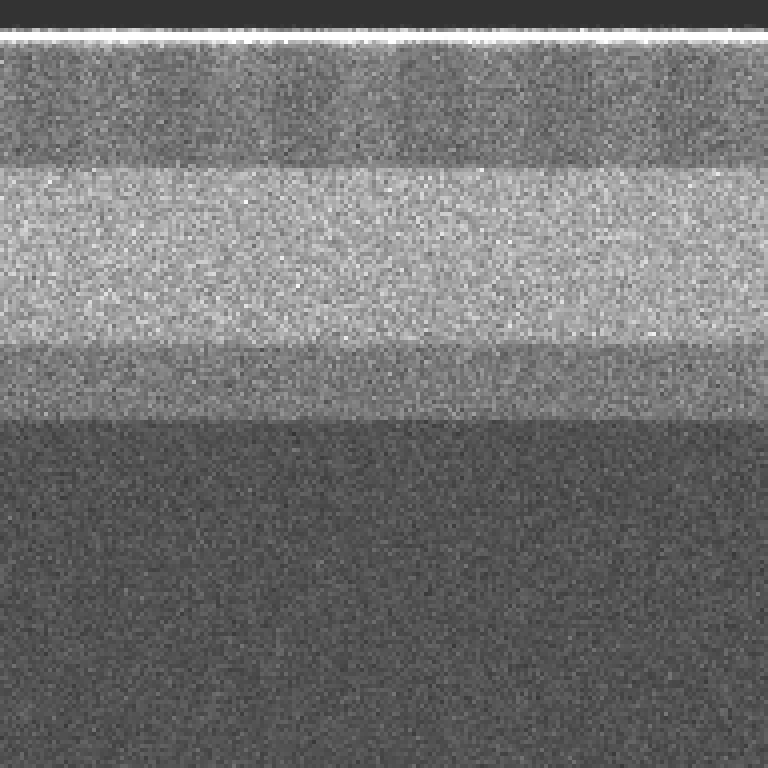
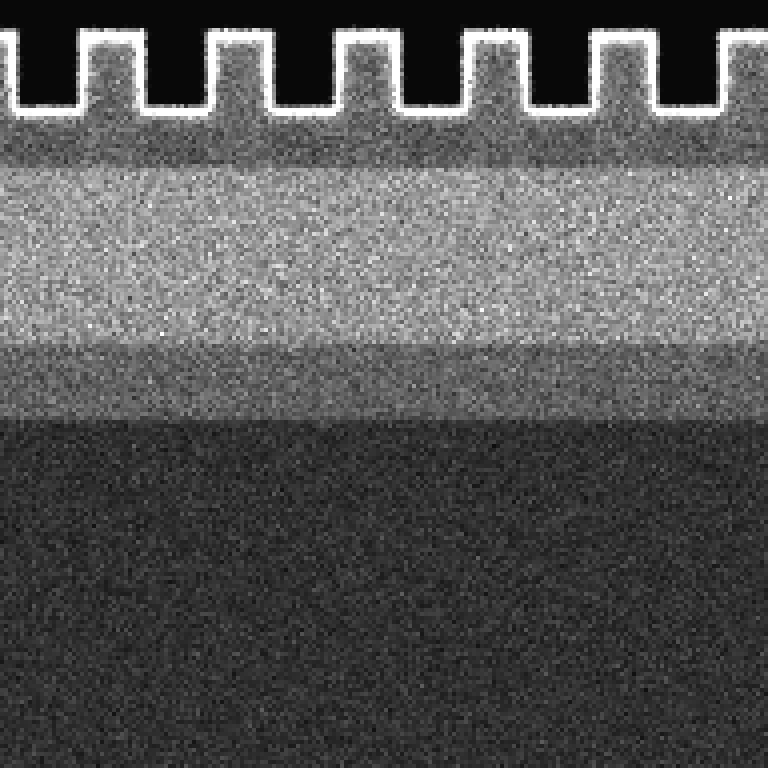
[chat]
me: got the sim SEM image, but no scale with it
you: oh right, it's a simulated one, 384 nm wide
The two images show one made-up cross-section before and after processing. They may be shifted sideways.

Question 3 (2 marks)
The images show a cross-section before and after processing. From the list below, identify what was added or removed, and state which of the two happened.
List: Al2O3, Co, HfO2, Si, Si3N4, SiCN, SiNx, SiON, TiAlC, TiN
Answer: SiNx was removed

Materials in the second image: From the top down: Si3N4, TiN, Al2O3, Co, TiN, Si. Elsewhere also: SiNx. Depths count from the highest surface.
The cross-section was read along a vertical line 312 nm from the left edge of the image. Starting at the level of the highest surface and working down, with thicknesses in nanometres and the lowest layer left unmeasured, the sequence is Si3N4 26, TiN 42, Al2O3 54, Co 34, TiN 38, Si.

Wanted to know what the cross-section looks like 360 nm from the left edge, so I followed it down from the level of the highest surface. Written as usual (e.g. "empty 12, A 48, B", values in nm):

Si3N4 26, TiN 42, Al2O3 54, Co 34, TiN 38, Si